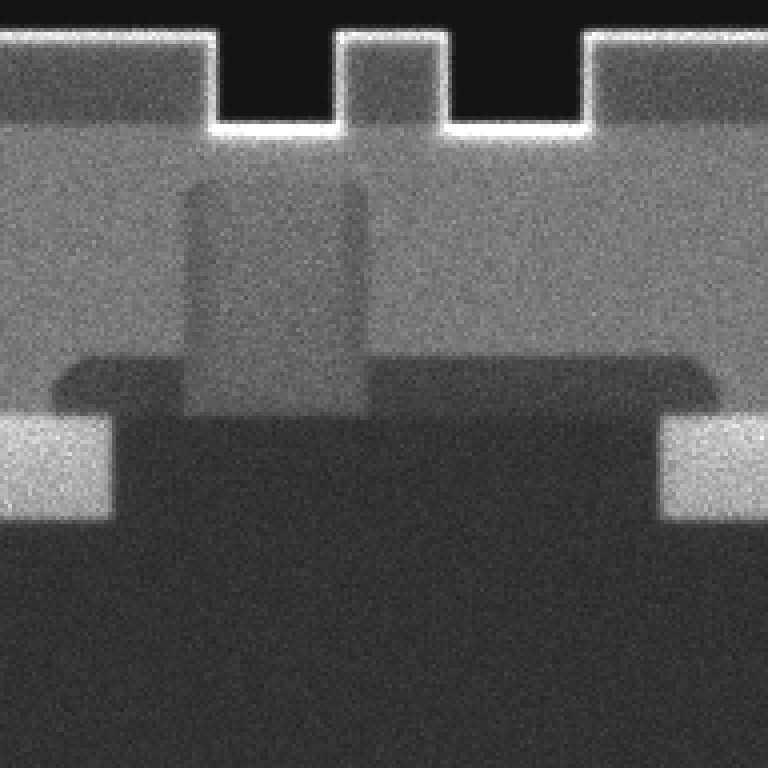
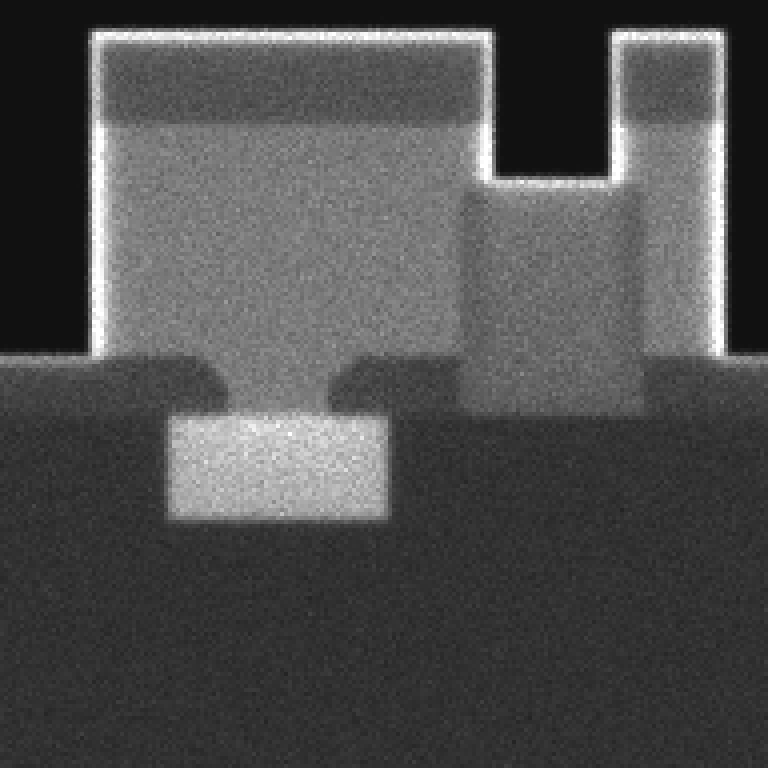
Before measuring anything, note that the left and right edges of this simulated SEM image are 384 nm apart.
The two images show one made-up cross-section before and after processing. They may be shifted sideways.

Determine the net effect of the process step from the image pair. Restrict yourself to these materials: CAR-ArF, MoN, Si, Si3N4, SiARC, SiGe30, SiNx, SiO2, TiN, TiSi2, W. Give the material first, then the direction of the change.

SiO2: removed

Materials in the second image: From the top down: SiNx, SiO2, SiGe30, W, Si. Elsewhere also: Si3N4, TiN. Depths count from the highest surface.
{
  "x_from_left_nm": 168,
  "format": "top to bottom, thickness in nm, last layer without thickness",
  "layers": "SiNx 46, SiO2 126, SiGe30 20, W 52, Si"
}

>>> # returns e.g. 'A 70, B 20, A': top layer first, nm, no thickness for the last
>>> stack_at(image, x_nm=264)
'empty 74, TiN 110, Si3N4 8, Si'